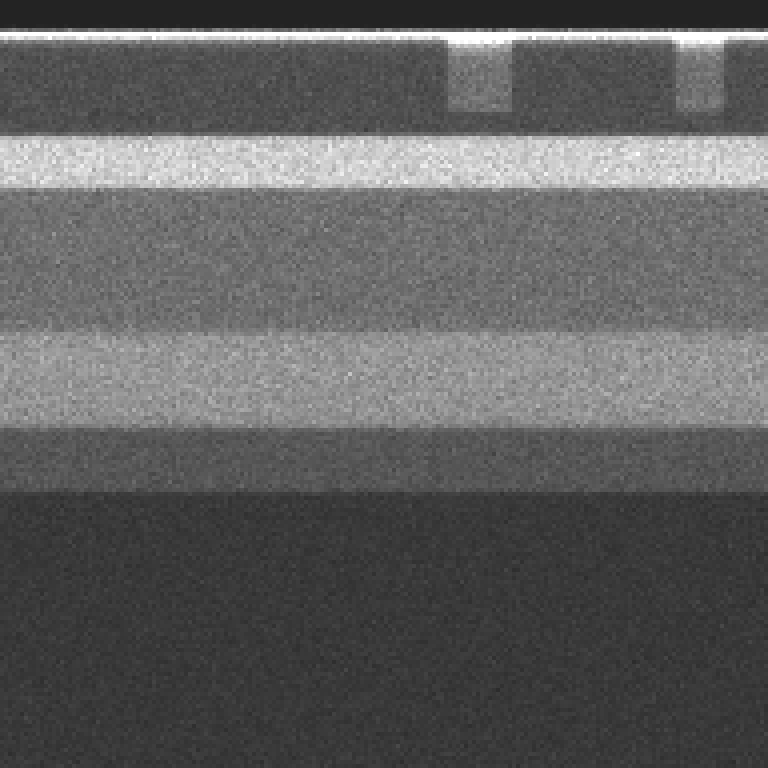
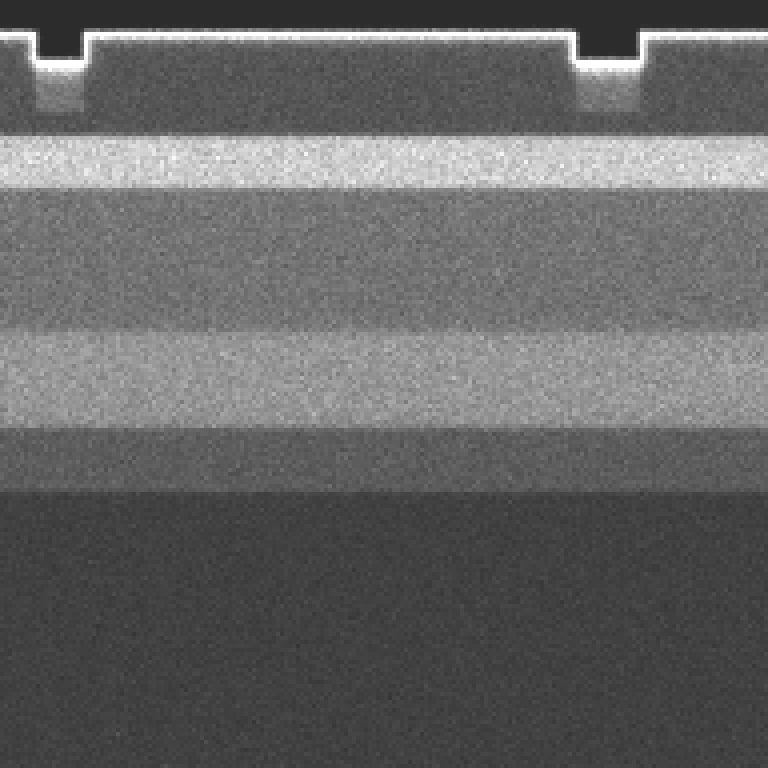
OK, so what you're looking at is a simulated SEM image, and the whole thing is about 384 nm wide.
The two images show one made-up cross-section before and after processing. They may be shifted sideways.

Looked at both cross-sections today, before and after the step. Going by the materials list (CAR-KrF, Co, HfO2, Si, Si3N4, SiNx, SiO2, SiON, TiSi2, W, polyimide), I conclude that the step removed SiO2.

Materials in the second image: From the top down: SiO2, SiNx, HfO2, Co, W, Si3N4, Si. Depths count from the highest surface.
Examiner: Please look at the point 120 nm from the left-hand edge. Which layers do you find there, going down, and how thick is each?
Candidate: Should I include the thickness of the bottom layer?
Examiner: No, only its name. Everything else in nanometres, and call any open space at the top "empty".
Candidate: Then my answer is SiNx 52, HfO2 26, Co 72, W 48, Si3N4 32, Si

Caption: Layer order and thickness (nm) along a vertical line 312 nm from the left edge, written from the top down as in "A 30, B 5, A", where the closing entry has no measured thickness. empty 14, SiO2 26, SiNx 12, HfO2 26, Co 72, W 48, Si3N4 32, Si